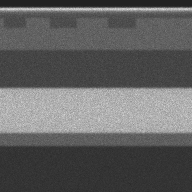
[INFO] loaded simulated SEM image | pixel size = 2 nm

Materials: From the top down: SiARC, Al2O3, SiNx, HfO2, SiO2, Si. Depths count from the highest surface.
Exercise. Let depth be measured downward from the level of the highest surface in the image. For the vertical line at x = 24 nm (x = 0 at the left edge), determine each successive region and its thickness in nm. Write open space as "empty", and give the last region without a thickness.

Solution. SiARC 40, Al2O3 44, SiNx 76, HfO2 90, SiO2 26, Si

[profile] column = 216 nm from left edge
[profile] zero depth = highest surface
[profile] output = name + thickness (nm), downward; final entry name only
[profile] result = SiARC 40, Al2O3 44, SiNx 76, HfO2 90, SiO2 26, Si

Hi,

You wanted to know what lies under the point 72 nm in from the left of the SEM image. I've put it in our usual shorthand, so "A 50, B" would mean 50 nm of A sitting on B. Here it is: SiARC 20, Al2O3 64, SiNx 76, HfO2 90, SiO2 26, Si